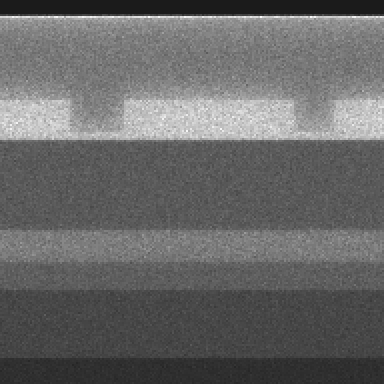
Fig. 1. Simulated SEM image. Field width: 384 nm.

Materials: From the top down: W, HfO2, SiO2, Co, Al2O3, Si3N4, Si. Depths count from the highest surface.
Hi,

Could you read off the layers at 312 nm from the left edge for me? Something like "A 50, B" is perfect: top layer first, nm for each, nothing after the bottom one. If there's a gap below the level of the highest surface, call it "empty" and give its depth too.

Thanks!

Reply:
W 116, HfO2 8, SiO2 90, Co 32, Al2O3 28, Si3N4 68, Si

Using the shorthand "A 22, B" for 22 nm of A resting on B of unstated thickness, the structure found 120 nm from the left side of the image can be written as W 116, HfO2 8, SiO2 90, Co 32, Al2O3 28, Si3N4 68, Si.